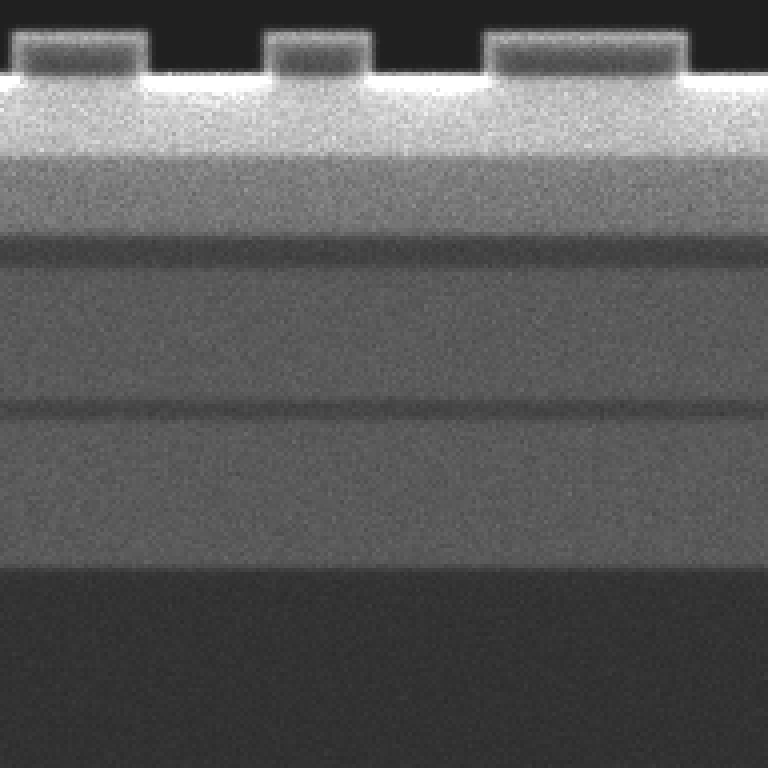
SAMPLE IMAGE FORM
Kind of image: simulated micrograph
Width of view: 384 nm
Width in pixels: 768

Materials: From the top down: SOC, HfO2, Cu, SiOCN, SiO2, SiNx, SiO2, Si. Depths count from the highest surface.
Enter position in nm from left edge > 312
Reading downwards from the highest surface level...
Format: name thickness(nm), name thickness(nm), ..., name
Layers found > SOC 22, HfO2 40, Cu 40, SiOCN 16, SiO2 66, SiNx 10, SiO2 74, Si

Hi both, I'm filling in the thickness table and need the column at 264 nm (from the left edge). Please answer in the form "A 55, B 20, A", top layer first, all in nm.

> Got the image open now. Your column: SOC 22, HfO2 40, Cu 40, SiOCN 16, SiO2 66, SiNx 10, SiO2 74, Si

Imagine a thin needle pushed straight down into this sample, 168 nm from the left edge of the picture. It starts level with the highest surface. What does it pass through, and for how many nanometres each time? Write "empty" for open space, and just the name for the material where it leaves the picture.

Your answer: SOC 22, HfO2 40, Cu 40, SiOCN 16, SiO2 66, SiNx 10, SiO2 74, Si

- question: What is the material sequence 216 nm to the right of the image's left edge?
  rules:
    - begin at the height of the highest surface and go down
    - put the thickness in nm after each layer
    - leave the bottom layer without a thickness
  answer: empty 22, HfO2 40, Cu 40, SiOCN 16, SiO2 66, SiNx 10, SiO2 74, Si